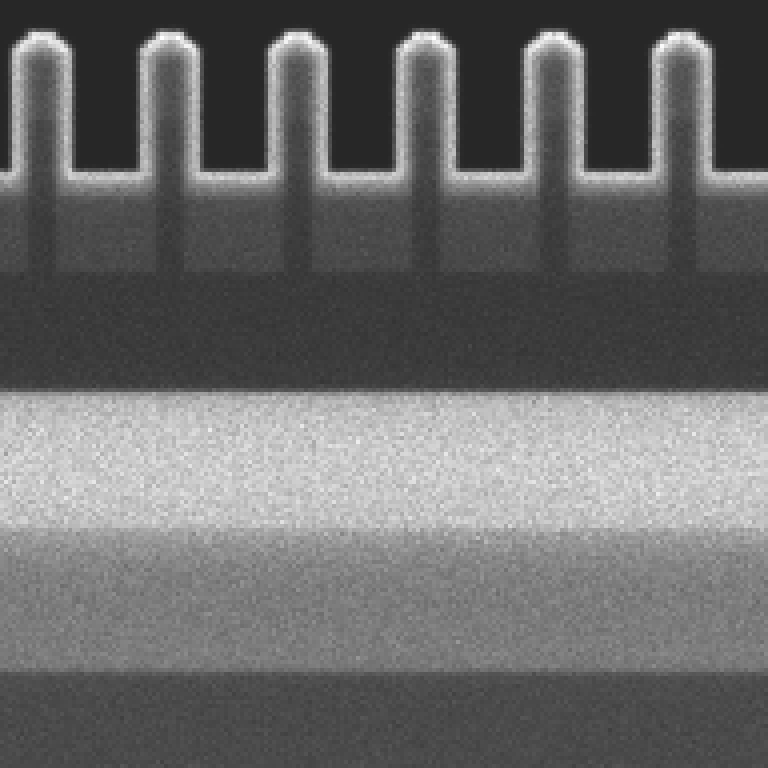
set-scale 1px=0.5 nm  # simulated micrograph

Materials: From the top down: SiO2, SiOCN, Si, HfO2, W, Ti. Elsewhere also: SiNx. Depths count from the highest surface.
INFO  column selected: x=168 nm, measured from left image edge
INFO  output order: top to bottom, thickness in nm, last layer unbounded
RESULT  empty 70, SiO2 12, SiNx 38, Si 60, HfO2 68, W 72, Ti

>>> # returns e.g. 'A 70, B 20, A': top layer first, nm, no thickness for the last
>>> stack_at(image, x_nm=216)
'SiO2 12, SiOCN 32, Si 136, HfO2 68, W 72, Ti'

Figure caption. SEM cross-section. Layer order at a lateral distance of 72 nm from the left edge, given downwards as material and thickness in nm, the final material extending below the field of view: empty 6, SiO2 76, SiNx 38, Si 60, HfO2 68, W 72, Ti